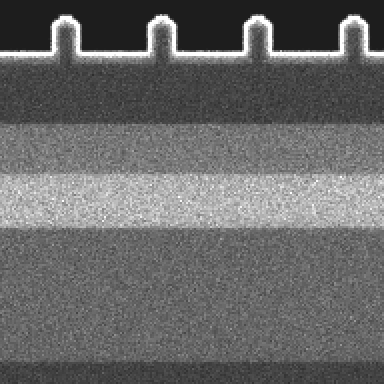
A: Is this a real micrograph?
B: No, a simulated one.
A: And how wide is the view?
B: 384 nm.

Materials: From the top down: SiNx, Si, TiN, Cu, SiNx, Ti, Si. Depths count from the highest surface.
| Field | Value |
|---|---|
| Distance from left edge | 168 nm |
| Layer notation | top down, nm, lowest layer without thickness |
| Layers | empty 4, SiNx 44, Si 60, TiN 50, Cu 54, SiNx 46, Ti 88, Si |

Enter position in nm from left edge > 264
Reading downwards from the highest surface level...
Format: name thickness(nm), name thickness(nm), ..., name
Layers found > empty 4, SiNx 44, Si 60, TiN 50, Cu 54, SiNx 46, Ti 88, Si